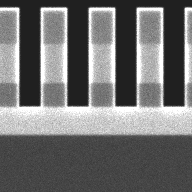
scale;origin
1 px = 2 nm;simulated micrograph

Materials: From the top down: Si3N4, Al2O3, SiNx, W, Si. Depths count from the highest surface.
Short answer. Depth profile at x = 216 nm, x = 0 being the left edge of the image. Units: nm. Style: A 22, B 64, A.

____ Si3N4 72, Al2O3 78, SiNx 48, W 56, Si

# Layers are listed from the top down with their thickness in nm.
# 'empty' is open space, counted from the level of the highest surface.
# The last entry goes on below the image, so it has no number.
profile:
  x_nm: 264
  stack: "empty 198, W 56, Si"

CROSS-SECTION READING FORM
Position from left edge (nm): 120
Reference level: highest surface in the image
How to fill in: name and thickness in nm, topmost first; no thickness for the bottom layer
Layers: Si3N4 72, Al2O3 78, SiNx 48, W 56, Si